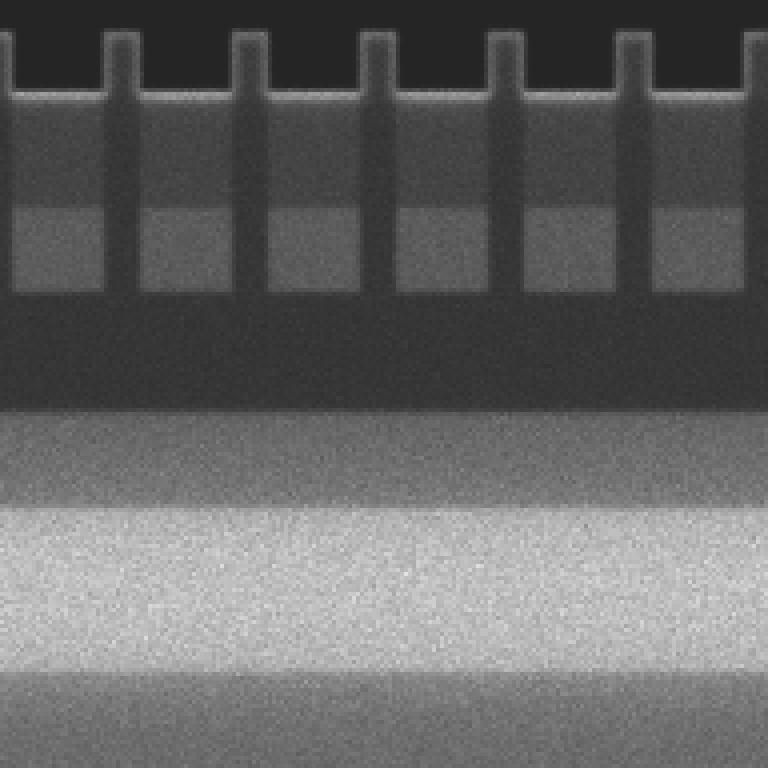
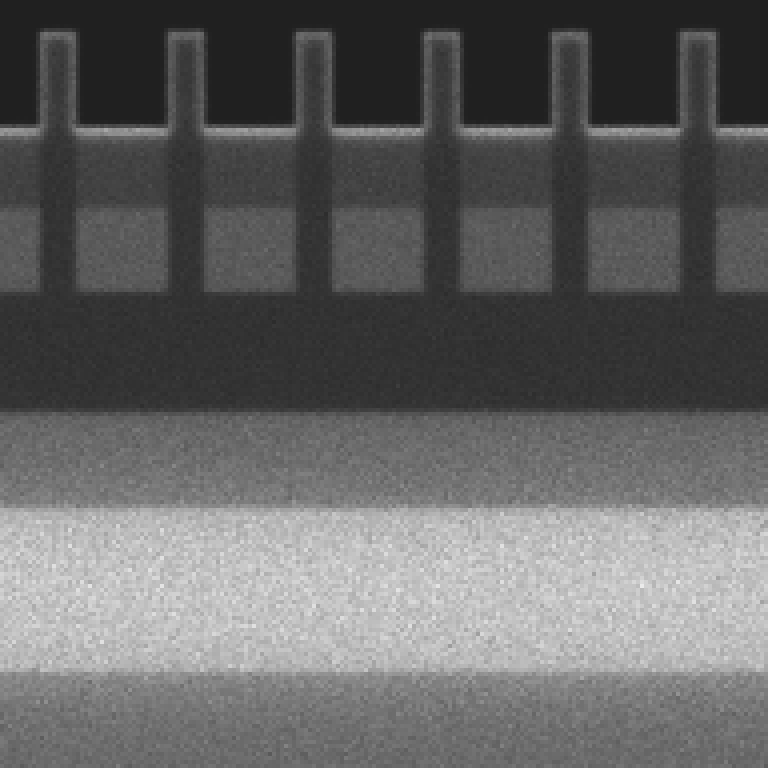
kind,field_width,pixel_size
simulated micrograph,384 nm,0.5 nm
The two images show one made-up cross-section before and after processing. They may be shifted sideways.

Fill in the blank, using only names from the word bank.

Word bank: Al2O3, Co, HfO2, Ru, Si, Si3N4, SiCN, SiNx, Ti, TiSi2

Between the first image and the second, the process removed SiNx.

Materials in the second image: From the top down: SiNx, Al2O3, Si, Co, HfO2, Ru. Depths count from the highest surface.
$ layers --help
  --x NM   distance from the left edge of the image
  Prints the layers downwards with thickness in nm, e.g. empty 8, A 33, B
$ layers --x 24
Si 190, Co 48, HfO2 82, Ru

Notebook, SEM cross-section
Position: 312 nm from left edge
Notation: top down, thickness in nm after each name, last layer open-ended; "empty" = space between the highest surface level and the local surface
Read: empty 48, SiNx 40, Al2O3 42, Si 60, Co 48, HfO2 82, Ru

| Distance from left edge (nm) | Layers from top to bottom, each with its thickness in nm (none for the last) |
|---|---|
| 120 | empty 48, SiNx 40, Al2O3 42, Si 60, Co 48, HfO2 82, Ru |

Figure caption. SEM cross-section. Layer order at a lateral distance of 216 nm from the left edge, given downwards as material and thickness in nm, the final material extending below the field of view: Si 190, Co 48, HfO2 82, Ru